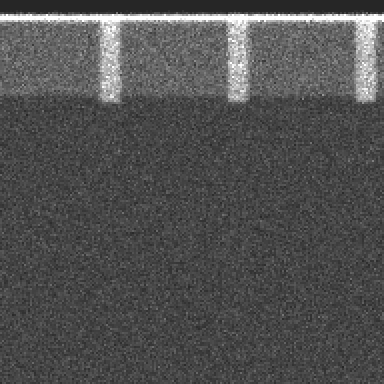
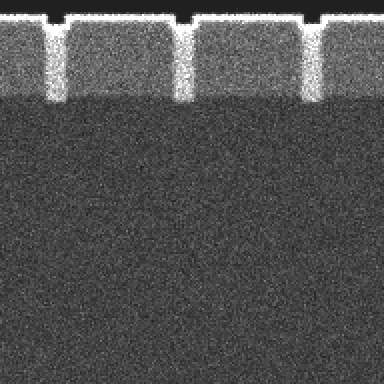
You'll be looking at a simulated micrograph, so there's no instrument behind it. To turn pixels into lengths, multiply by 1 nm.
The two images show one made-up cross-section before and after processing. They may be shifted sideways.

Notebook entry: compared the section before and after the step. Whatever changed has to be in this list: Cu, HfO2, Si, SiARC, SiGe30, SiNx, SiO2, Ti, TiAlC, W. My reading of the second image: W removed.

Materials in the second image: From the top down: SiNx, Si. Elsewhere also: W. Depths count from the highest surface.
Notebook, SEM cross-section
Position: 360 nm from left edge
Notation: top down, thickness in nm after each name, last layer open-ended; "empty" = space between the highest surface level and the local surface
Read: SiNx 80, Si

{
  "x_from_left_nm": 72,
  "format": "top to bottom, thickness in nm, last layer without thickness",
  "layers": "SiNx 80, Si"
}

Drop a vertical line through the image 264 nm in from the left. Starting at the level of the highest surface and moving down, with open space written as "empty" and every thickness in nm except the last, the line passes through SiNx 80, Si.